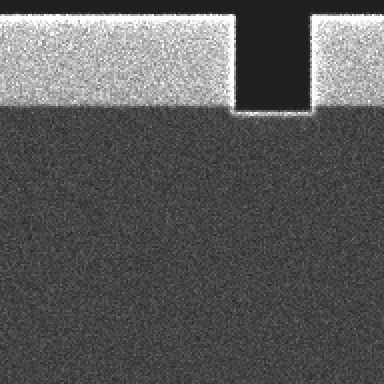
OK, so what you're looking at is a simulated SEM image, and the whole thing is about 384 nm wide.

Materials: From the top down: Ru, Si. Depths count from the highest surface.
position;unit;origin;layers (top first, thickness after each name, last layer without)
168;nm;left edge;Ru 90, Si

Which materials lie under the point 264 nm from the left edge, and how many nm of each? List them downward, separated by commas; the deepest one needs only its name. empty 96, Si